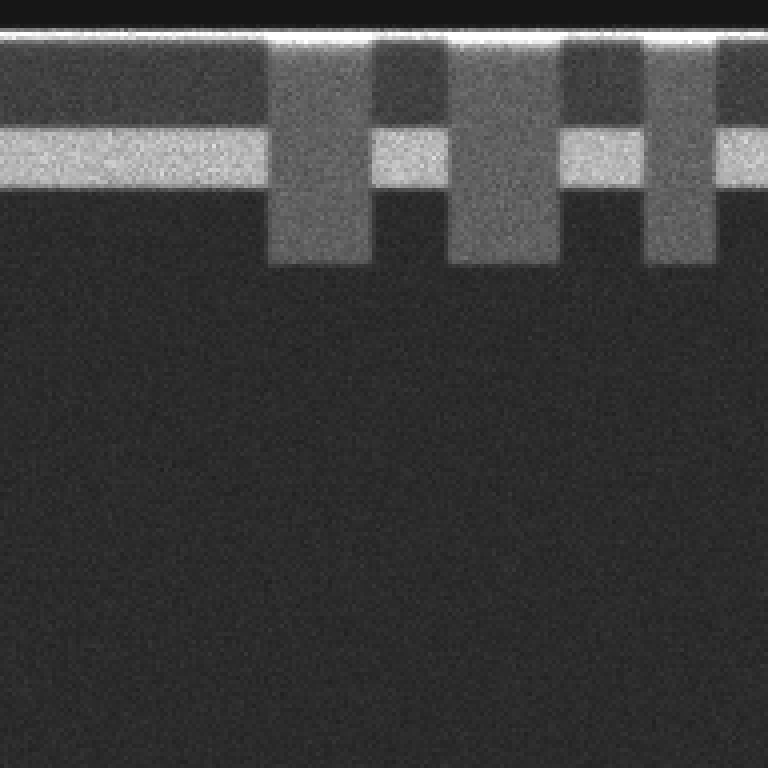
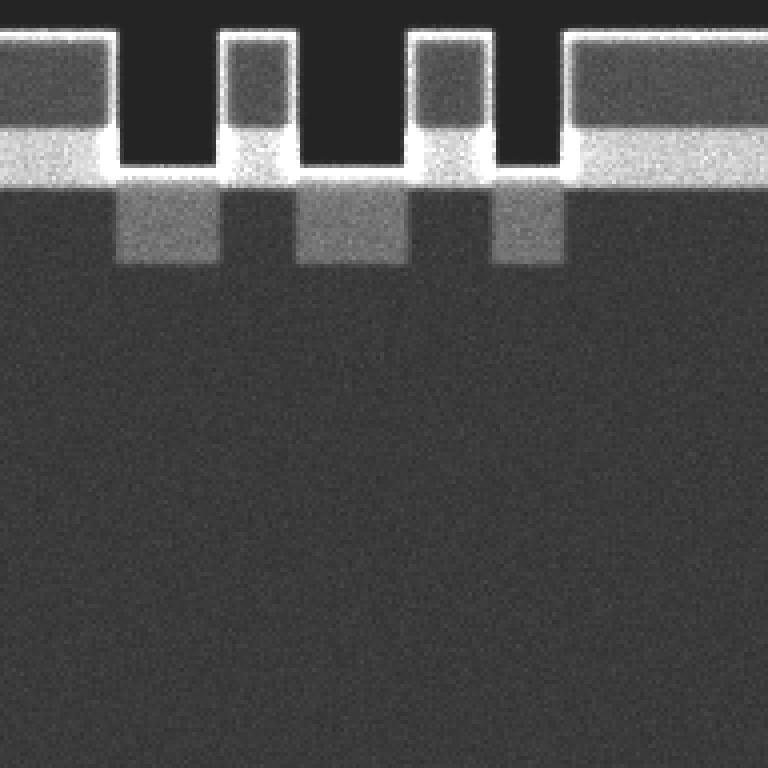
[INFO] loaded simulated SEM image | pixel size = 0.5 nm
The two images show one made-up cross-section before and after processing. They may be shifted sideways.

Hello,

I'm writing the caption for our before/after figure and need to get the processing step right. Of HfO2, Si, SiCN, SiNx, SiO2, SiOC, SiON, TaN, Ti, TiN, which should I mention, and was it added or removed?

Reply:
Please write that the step removed SiO2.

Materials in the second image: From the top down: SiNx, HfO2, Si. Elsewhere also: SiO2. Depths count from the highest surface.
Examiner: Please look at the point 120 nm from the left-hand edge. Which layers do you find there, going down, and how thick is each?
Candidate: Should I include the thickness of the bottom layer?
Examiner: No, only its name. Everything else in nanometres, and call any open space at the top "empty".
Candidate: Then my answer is SiNx 48, HfO2 30, Si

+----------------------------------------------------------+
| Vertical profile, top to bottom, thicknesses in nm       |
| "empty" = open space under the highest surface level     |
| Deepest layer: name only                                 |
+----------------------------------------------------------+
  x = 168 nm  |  empty 68, SiO2 48, Si